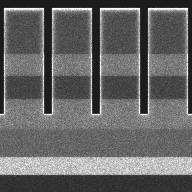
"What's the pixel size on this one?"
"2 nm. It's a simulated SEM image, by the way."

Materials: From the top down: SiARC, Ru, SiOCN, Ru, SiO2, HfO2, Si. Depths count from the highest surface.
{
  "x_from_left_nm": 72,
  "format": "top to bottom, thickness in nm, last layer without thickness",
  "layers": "SiARC 92, Ru 44, SiOCN 46, Ru 60, SiO2 56, HfO2 36, Si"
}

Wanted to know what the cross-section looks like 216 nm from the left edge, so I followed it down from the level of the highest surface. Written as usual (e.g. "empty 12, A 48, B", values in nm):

SiARC 92, Ru 44, SiOCN 46, Ru 60, SiO2 56, HfO2 36, Si